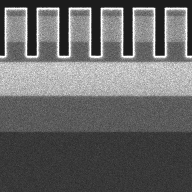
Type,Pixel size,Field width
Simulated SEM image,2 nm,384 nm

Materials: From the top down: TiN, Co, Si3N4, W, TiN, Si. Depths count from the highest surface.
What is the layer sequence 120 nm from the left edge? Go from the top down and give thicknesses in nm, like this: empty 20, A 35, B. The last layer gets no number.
empty 96, Si3N4 12, W 68, TiN 72, Si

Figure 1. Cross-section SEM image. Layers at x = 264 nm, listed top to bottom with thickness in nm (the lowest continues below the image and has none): empty 96, Si3N4 12, W 68, TiN 72, Si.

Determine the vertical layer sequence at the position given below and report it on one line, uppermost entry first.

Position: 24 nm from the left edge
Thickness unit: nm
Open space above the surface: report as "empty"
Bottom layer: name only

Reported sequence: TiN 16, Co 52, Si3N4 40, W 68, TiN 72, Si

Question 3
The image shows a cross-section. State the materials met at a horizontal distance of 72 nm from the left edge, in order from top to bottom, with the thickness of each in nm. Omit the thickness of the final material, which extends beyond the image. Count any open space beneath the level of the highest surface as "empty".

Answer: empty 96, Si3N4 12, W 68, TiN 72, Si